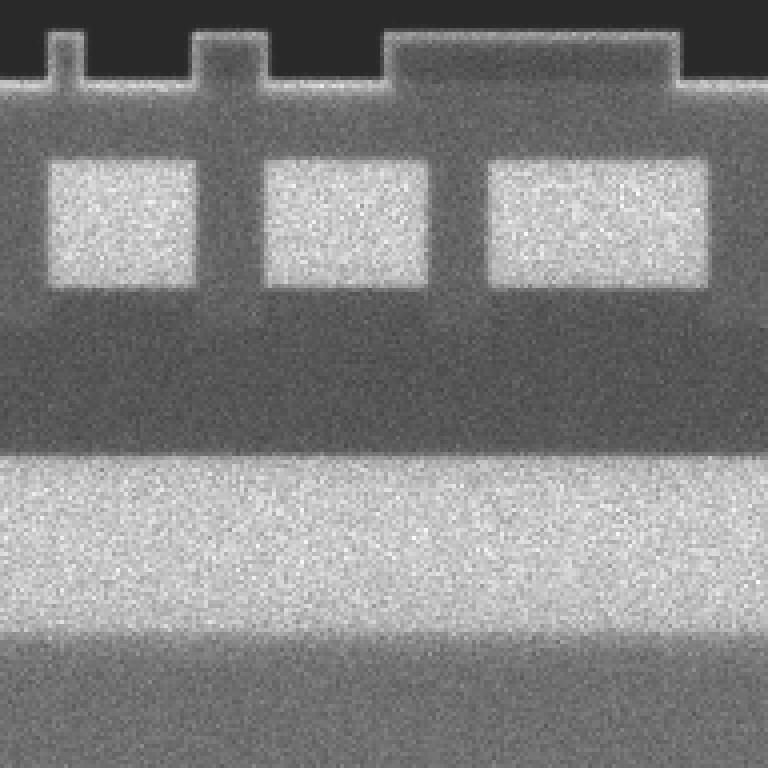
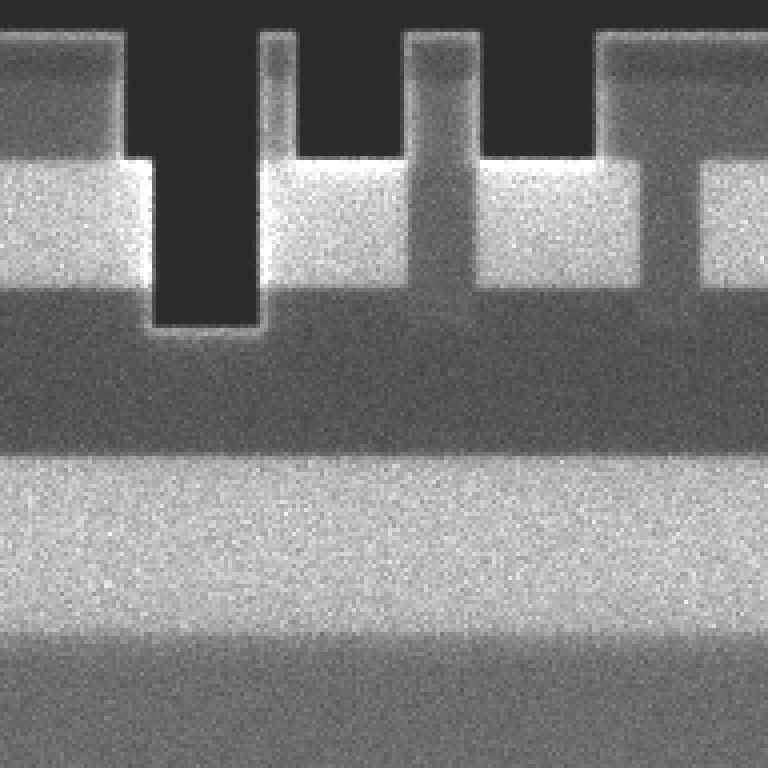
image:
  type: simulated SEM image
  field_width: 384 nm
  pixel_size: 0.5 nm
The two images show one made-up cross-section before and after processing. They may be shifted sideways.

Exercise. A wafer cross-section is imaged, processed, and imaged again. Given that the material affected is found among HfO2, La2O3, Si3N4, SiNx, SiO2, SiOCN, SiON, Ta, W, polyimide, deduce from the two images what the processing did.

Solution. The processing removed SiO2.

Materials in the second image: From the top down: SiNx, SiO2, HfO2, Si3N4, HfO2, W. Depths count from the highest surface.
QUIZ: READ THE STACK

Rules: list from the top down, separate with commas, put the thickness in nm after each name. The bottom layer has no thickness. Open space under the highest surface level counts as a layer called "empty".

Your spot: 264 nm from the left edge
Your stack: empty 64, HfO2 64, Si3N4 84, HfO2 88, W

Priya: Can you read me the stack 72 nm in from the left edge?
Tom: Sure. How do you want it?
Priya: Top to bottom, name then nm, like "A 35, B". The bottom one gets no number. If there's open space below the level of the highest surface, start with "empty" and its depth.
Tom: empty 64, HfO2 64, Si3N4 84, HfO2 88, W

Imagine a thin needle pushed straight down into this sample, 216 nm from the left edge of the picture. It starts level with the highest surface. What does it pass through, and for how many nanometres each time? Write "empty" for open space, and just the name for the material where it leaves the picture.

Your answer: SiNx 24, SiO2 124, Si3N4 64, HfO2 88, W